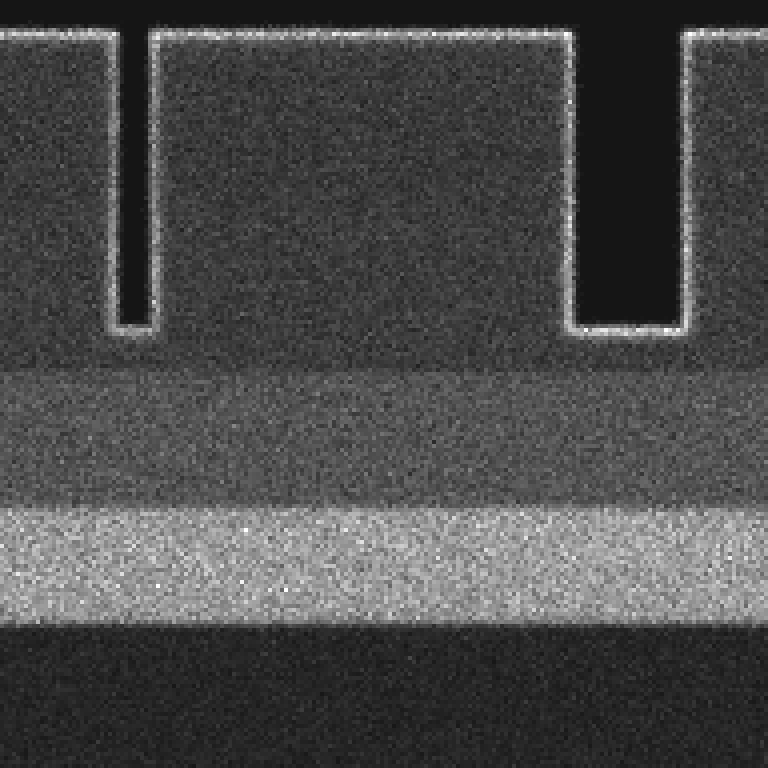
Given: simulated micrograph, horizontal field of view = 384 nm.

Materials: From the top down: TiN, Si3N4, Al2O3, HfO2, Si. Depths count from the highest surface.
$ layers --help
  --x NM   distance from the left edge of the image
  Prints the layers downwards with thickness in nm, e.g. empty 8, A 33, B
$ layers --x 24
TiN 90, Si3N4 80, Al2O3 68, HfO2 58, Si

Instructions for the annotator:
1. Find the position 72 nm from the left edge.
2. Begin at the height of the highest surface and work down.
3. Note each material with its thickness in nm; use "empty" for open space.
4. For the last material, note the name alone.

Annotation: empty 148, Si3N4 22, Al2O3 68, HfO2 58, Si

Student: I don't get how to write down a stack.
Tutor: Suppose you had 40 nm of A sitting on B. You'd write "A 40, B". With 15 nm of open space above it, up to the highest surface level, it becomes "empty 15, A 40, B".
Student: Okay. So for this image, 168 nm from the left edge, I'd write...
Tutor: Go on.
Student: TiN 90, Si3N4 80, Al2O3 68, HfO2 58, Si